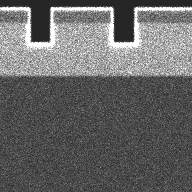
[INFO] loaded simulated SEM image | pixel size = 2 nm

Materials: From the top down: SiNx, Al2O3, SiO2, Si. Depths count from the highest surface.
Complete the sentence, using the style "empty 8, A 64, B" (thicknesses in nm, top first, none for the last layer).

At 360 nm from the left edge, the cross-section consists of SiNx 30, Al2O3 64, SiO2 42, Si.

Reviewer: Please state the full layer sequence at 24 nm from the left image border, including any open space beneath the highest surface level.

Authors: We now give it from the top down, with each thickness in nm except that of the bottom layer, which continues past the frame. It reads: SiNx 30, Al2O3 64, SiO2 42, Si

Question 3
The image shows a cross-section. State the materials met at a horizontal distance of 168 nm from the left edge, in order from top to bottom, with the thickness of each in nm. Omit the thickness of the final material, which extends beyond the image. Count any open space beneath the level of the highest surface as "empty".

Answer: SiNx 30, Al2O3 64, SiO2 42, Si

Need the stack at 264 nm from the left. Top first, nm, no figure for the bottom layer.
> empty 70, Al2O3 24, SiO2 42, Si